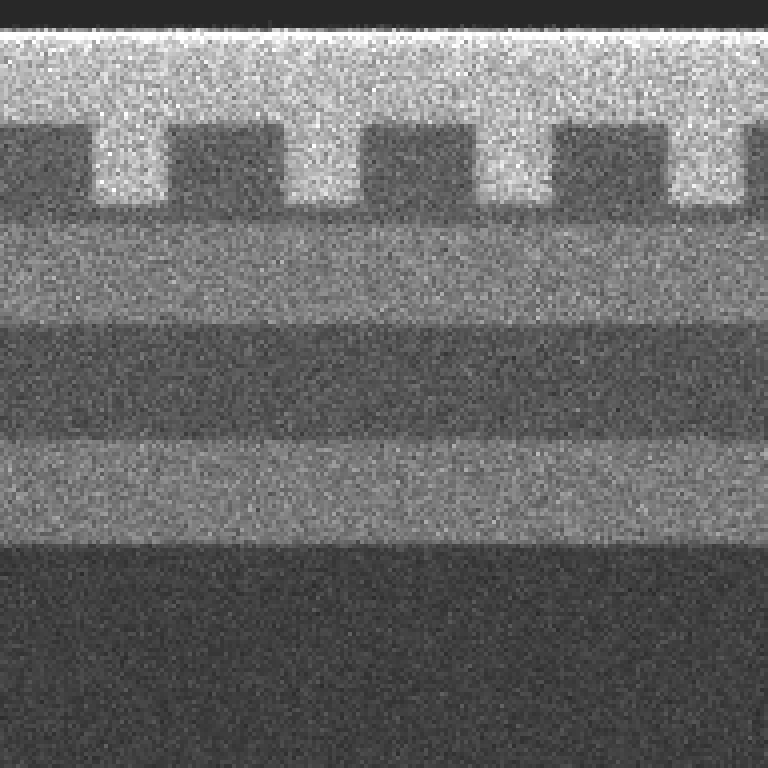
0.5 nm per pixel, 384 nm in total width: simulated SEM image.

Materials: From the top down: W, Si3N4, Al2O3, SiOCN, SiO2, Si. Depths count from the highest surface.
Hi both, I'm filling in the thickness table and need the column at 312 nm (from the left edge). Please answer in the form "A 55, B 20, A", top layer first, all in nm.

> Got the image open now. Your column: W 46, Si3N4 50, Al2O3 50, SiOCN 58, SiO2 52, Si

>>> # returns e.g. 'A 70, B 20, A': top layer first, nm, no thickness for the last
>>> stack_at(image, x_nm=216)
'W 46, Si3N4 50, Al2O3 50, SiOCN 58, SiO2 52, Si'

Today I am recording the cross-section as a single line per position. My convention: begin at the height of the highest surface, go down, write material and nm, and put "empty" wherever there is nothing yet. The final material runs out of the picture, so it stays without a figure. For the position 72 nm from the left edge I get W 86, Si3N4 10, Al2O3 50, SiOCN 58, SiO2 52, Si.